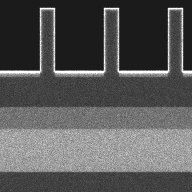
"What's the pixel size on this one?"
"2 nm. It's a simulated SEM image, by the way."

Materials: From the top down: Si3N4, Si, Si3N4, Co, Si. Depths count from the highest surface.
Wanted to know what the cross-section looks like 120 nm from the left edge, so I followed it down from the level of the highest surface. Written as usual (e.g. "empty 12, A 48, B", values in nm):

empty 126, Si3N4 12, Si 60, Si3N4 44, Co 86, Si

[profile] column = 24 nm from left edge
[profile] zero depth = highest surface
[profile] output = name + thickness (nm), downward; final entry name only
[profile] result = empty 126, Si3N4 12, Si 60, Si3N4 44, Co 86, Si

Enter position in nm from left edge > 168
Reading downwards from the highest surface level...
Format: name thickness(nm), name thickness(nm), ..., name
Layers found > empty 126, Si3N4 12, Si 60, Si3N4 44, Co 86, Si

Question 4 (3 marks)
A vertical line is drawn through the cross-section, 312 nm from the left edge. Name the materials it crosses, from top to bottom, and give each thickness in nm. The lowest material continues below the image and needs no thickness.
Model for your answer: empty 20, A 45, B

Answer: empty 126, Si3N4 12, Si 60, Si3N4 44, Co 86, Si